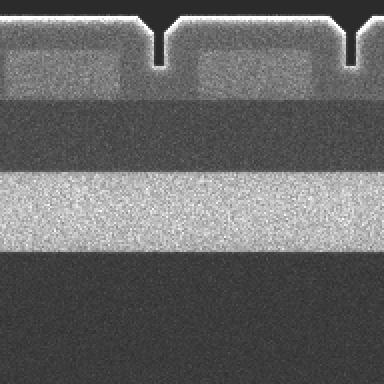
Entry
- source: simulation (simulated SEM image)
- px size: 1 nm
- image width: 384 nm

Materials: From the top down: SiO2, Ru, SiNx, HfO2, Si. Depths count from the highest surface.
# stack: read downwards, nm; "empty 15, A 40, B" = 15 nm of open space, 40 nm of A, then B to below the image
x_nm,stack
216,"SiO2 34, Ru 50, SiNx 72, HfO2 80, Si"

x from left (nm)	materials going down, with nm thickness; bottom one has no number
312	SiO2 84, SiNx 72, HfO2 80, Si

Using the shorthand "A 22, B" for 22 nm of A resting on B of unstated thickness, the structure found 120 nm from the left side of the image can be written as SiO2 84, SiNx 72, HfO2 80, Si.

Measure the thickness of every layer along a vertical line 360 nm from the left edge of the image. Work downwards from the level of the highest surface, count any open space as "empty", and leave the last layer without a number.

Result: empty 12, SiO2 72, SiNx 72, HfO2 80, Si